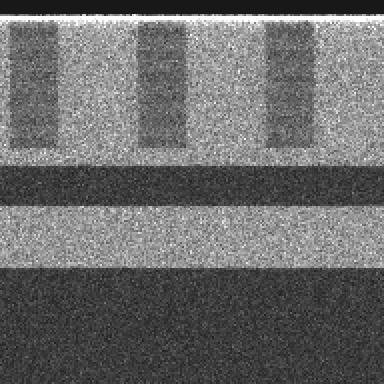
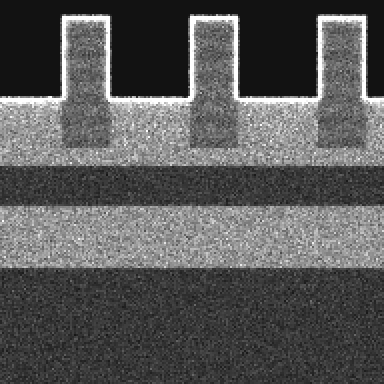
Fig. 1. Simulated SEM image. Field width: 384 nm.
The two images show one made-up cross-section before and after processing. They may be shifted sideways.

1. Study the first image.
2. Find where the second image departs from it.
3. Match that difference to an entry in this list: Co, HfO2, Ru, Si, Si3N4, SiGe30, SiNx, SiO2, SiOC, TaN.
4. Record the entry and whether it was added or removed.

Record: Co / removed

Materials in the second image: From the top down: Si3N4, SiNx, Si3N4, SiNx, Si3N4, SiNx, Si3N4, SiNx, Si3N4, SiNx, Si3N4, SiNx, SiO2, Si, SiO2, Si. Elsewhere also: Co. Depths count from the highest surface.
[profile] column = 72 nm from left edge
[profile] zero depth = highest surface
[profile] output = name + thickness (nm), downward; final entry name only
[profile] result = Si3N4 12, SiNx 10, Si3N4 12, SiNx 10, Si3N4 12, SiNx 10, Si3N4 12, SiNx 10, Si3N4 12, SiNx 10, Si3N4 12, SiNx 10, SiO2 18, Si 40, SiO2 62, Si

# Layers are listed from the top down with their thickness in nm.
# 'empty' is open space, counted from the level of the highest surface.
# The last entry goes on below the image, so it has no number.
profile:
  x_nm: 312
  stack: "empty 82, Co 68, Si 40, SiO2 62, Si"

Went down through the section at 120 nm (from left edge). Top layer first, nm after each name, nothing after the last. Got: empty 82, Co 68, Si 40, SiO2 62, Si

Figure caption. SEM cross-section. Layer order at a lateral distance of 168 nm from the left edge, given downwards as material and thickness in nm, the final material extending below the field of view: empty 82, Co 68, Si 40, SiO2 62, Si